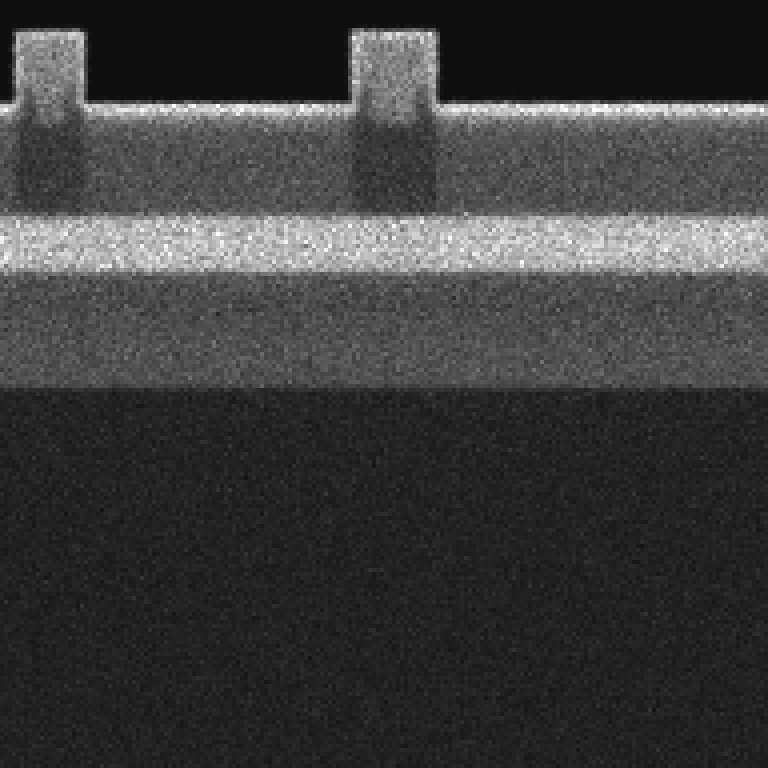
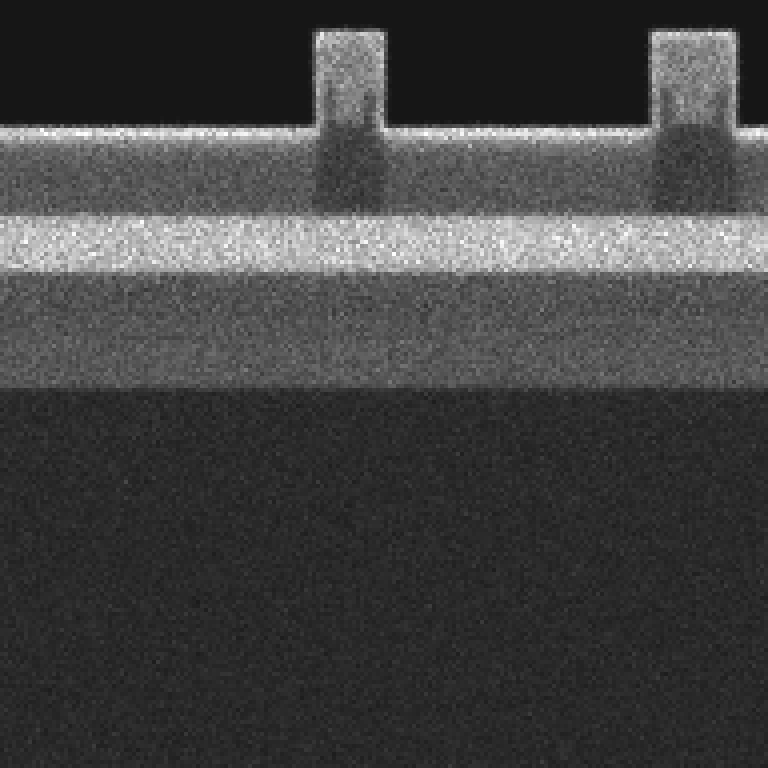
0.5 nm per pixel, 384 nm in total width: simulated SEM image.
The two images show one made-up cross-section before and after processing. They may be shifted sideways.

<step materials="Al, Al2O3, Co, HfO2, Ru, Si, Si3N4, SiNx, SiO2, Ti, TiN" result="removed SiO2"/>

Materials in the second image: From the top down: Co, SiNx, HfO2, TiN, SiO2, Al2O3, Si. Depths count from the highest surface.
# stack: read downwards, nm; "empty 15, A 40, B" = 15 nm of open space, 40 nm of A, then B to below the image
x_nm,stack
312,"empty 48, SiO2 44, HfO2 28, TiN 22, SiO2 12, Al2O3 24, Si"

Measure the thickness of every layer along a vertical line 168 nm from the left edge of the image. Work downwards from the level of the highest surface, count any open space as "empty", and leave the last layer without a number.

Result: Co 46, SiNx 46, HfO2 28, TiN 22, SiO2 12, Al2O3 24, Si